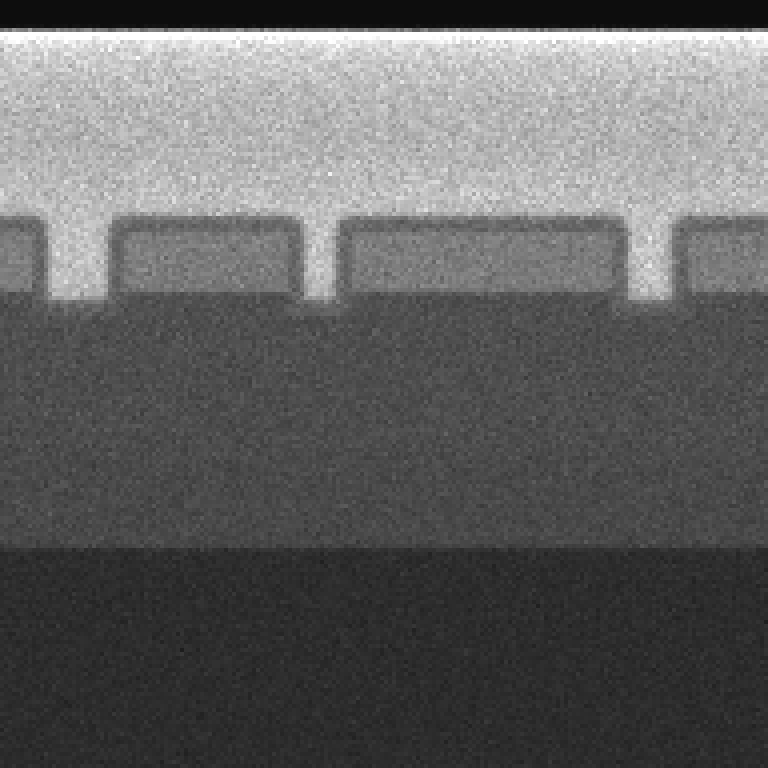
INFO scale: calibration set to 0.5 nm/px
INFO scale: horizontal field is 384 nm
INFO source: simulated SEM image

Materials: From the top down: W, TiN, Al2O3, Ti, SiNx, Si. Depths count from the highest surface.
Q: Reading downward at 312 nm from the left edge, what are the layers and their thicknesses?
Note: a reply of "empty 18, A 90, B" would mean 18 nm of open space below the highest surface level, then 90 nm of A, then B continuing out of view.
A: W 96, TiN 46, Ti 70, SiNx 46, Si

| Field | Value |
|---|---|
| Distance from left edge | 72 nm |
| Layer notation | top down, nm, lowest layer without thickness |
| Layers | W 92, TiN 8, Al2O3 30, Ti 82, SiNx 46, Si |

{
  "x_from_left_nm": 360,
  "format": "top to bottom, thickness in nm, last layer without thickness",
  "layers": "W 92, TiN 8, Al2O3 30, Ti 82, SiNx 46, Si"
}